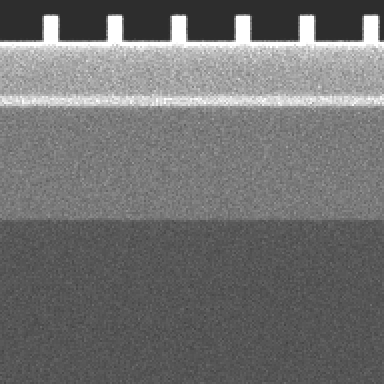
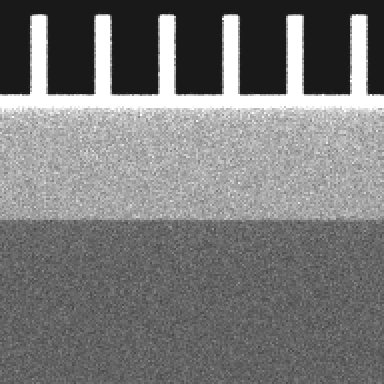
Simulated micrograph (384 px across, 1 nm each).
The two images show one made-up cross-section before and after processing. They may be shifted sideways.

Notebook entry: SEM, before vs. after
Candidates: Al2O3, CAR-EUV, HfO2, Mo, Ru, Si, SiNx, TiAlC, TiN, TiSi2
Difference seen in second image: TiN removed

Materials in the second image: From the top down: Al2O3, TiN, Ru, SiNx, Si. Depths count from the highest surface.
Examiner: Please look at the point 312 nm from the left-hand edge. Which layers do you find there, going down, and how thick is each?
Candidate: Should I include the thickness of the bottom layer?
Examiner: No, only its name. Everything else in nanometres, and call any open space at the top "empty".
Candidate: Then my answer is empty 80, Ru 10, SiNx 114, Si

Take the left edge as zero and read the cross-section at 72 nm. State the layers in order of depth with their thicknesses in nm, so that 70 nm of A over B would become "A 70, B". empty 80, Ru 10, SiNx 114, Si